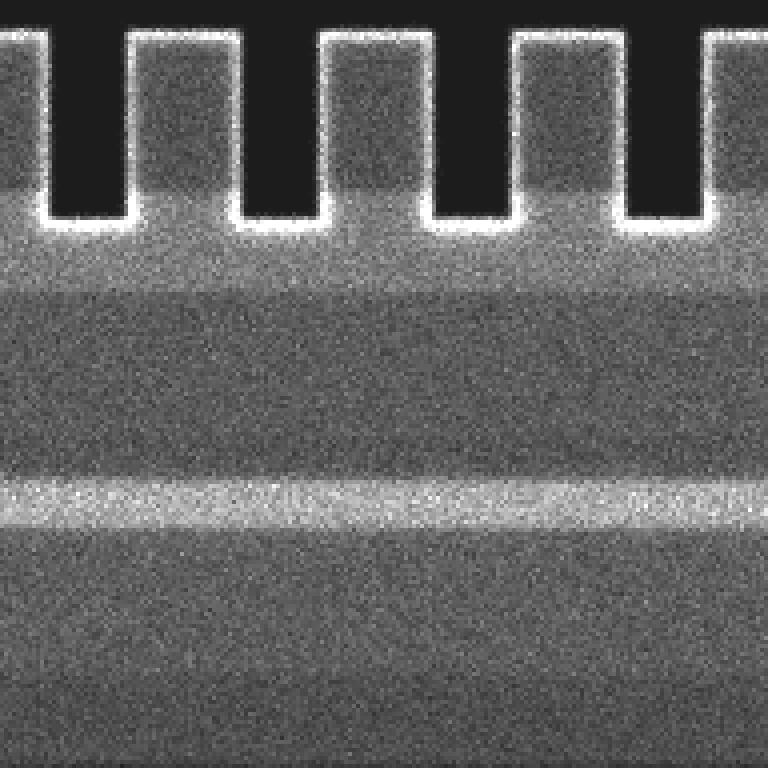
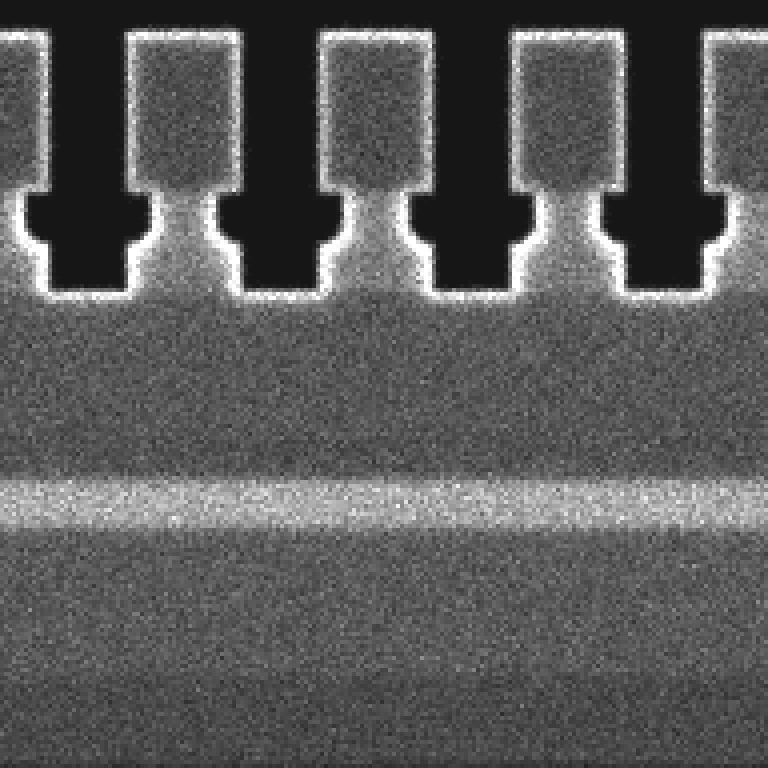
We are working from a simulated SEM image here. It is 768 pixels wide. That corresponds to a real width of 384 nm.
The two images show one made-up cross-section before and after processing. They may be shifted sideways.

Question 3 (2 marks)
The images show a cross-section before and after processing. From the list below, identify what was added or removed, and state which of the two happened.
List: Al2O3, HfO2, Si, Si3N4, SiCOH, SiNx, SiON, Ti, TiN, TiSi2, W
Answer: Al2O3 was removed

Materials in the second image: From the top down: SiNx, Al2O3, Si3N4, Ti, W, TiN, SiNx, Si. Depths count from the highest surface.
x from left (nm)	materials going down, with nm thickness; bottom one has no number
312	empty 130, Si3N4 72, Ti 22, W 24, TiN 74, SiNx 44, Si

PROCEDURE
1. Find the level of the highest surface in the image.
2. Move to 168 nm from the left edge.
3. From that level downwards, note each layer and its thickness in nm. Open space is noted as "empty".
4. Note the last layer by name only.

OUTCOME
SiNx 80, empty 22, Al2O3 28, Si3N4 72, Ti 22, W 24, TiN 74, SiNx 44, Si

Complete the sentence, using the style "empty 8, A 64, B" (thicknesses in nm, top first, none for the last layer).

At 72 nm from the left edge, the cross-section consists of SiNx 80, empty 22, Al2O3 28, Si3N4 72, Ti 22, W 24, TiN 74, SiNx 44, Si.